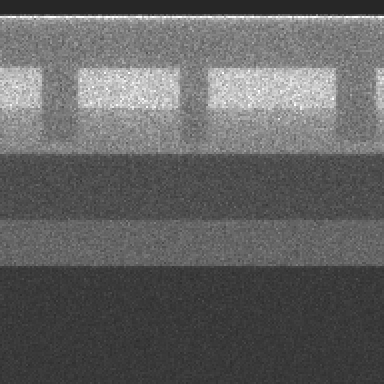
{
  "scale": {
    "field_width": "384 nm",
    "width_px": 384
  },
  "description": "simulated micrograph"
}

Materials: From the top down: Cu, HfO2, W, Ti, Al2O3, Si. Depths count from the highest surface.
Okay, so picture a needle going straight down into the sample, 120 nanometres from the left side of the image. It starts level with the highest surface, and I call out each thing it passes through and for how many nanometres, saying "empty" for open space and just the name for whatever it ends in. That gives Cu 52, HfO2 40, W 46, Ti 66, Al2O3 46, Si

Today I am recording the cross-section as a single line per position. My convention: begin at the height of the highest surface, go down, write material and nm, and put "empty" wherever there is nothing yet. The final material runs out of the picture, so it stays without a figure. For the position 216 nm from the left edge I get Cu 52, HfO2 40, W 46, Ti 66, Al2O3 46, Si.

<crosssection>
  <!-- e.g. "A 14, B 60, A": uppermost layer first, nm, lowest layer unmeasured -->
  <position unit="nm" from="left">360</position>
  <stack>Cu 126, W 12, Ti 66, Al2O3 46, Si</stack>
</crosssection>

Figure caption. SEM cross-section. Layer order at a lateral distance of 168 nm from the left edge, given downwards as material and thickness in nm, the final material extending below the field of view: Cu 52, HfO2 40, W 46, Ti 66, Al2O3 46, Si